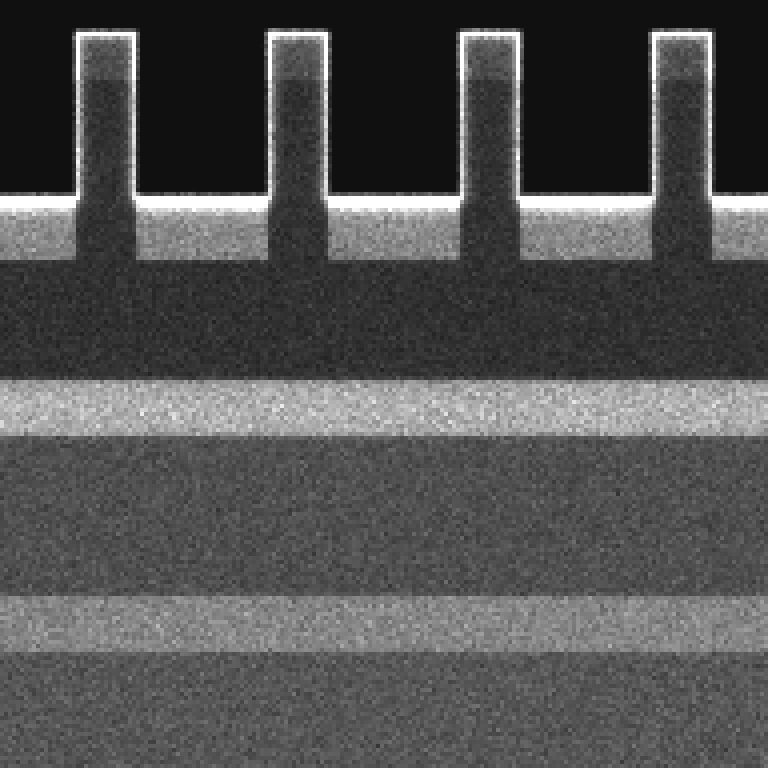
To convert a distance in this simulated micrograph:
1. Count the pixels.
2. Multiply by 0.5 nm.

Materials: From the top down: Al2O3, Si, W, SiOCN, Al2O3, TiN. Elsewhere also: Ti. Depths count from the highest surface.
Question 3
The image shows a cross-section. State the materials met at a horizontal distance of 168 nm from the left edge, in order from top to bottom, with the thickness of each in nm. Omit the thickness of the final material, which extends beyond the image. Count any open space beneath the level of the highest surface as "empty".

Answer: empty 82, Al2O3 32, Si 60, W 28, SiOCN 80, Al2O3 28, TiN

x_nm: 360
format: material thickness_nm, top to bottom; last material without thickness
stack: empty 82, Al2O3 32, Si 60, W 28, SiOCN 80, Al2O3 28, TiN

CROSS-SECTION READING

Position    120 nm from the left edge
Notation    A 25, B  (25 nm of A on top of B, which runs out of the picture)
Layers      empty 82, Al2O3 32, Si 60, W 28, SiOCN 80, Al2O3 28, TiN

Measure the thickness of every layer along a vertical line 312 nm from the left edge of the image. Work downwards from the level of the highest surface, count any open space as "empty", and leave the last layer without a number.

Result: empty 82, Al2O3 32, Si 60, W 28, SiOCN 80, Al2O3 28, TiN